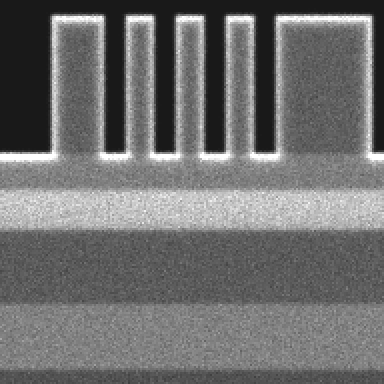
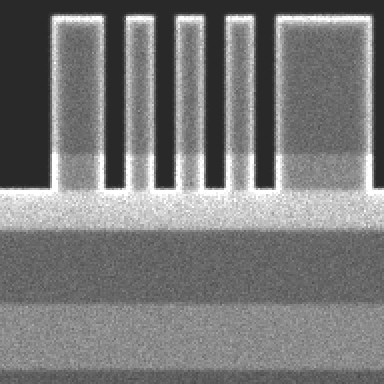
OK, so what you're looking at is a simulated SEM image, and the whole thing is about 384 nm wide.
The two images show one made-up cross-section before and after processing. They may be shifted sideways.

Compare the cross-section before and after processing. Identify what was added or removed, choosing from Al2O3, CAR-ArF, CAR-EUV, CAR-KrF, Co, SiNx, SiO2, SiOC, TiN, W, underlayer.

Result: SiO2 removed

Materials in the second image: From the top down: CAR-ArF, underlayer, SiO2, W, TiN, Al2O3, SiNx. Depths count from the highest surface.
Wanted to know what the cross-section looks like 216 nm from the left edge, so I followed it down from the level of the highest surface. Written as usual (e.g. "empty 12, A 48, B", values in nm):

empty 174, W 40, TiN 74, Al2O3 66, SiNx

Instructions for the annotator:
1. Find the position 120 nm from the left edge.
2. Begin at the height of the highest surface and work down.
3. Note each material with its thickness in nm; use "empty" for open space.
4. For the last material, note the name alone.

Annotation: empty 174, W 40, TiN 74, Al2O3 66, SiNx